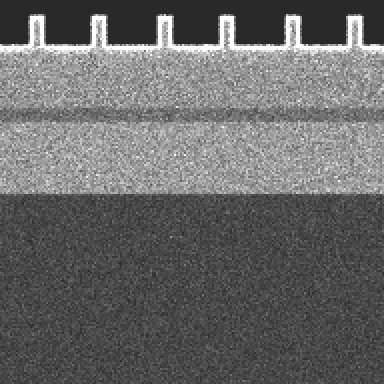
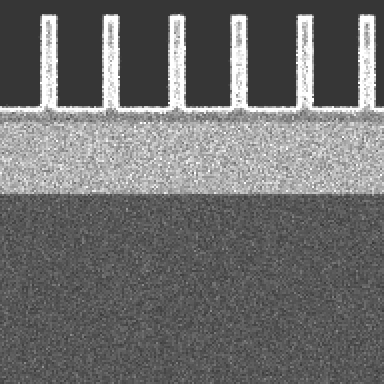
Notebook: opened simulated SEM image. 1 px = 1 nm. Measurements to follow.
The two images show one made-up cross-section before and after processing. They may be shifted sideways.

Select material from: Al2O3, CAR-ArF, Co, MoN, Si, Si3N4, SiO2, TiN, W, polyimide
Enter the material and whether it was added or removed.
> Co / removed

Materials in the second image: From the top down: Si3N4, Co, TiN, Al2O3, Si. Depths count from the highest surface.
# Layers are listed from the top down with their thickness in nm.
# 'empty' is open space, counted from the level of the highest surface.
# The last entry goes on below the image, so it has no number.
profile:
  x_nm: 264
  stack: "empty 92, TiN 14, Al2O3 72, Si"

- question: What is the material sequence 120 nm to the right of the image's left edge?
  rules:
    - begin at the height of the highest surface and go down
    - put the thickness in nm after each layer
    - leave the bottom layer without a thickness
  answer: empty 92, TiN 14, Al2O3 72, Si